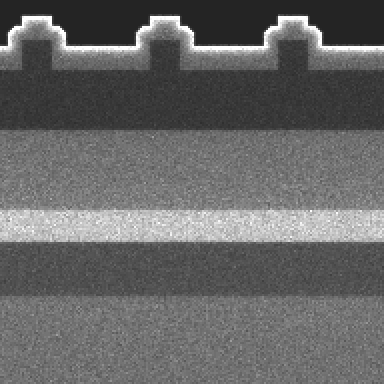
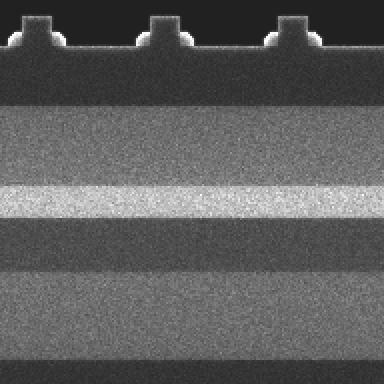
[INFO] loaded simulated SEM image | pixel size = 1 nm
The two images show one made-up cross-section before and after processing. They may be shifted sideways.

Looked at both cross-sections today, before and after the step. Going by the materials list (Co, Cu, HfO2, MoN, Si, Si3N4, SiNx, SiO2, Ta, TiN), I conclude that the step removed SiO2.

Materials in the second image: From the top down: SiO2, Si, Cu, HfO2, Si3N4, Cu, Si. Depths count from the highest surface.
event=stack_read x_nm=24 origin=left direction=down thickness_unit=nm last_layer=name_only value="Si 90, Cu 80, HfO2 32, Si3N4 54, Cu 88, Si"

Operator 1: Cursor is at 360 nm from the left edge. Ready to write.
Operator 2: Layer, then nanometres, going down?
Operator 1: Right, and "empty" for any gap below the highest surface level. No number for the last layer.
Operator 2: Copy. empty 30, Si 60, Cu 80, HfO2 32, Si3N4 54, Cu 88, Si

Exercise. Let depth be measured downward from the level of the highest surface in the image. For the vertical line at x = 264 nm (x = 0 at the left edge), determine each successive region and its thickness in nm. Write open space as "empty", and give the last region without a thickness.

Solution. empty 22, SiO2 8, Si 60, Cu 80, HfO2 32, Si3N4 54, Cu 88, Si